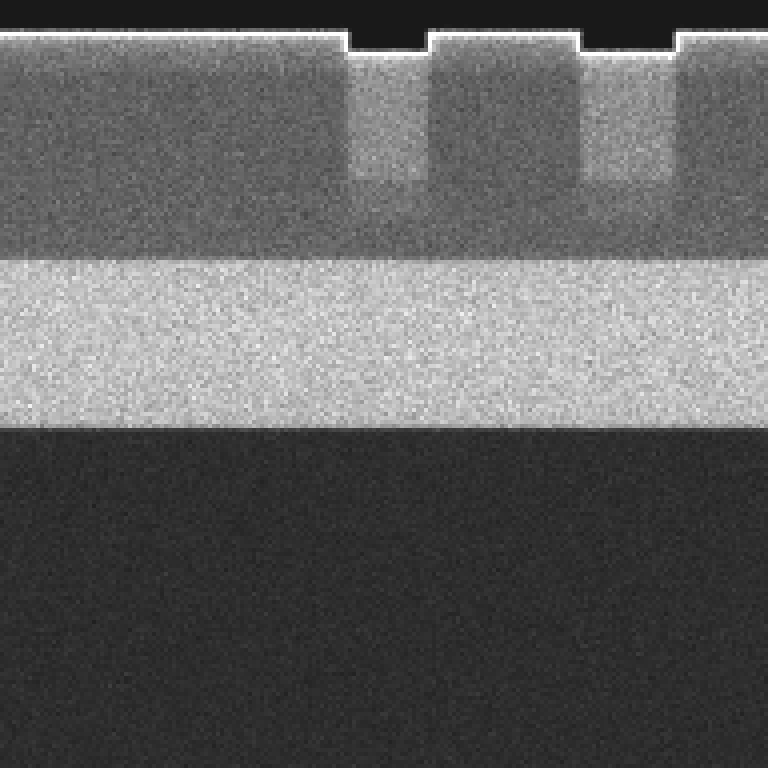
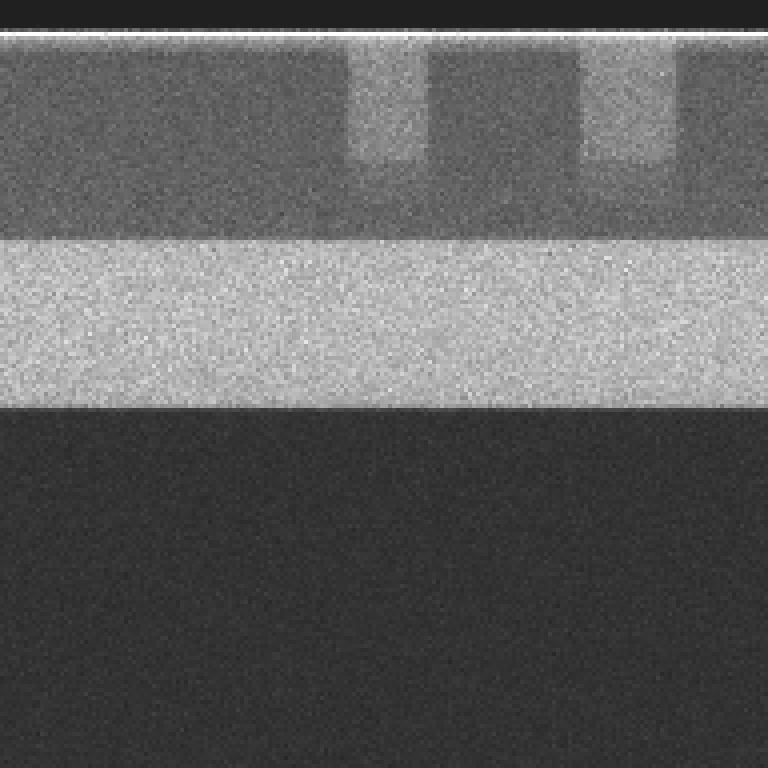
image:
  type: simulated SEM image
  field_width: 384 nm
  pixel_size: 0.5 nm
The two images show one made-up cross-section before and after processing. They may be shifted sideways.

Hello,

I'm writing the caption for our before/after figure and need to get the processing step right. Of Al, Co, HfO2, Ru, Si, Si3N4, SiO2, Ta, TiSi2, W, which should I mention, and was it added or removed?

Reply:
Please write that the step removed Ru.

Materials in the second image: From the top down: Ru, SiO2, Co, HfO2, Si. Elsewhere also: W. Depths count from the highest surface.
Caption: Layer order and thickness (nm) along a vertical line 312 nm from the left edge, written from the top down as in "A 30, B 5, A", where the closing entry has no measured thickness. W 64, Ru 20, Co 20, HfO2 84, Si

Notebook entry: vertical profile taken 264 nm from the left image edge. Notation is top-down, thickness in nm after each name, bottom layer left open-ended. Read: Ru 10, SiO2 62, Co 32, HfO2 84, Si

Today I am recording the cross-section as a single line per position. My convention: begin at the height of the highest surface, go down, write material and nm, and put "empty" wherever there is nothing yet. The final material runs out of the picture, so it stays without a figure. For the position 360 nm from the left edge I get Ru 10, SiO2 62, Co 32, HfO2 84, Si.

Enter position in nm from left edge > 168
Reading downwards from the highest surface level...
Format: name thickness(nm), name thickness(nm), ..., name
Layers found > Ru 10, SiO2 62, Co 32, HfO2 84, Si